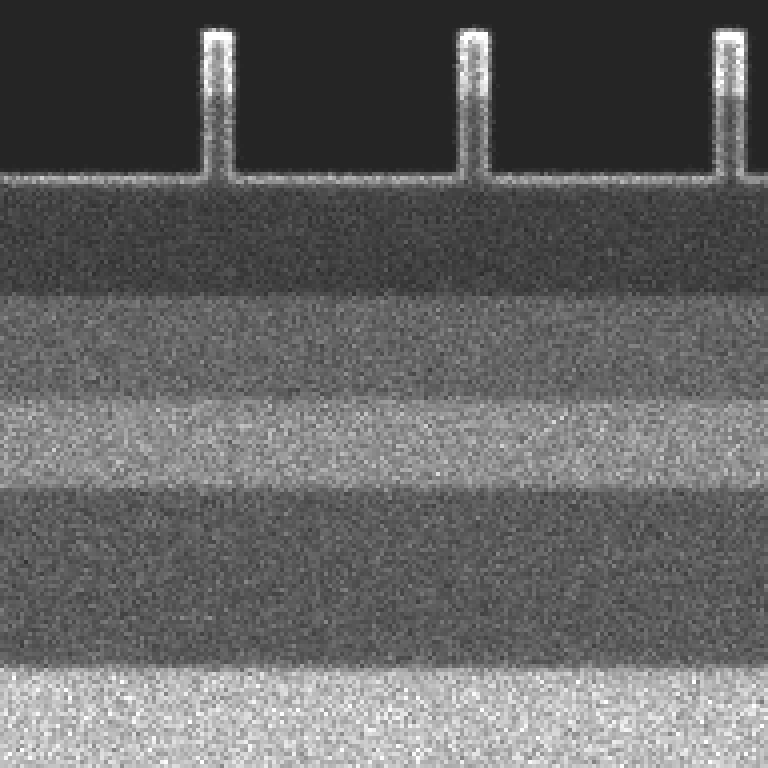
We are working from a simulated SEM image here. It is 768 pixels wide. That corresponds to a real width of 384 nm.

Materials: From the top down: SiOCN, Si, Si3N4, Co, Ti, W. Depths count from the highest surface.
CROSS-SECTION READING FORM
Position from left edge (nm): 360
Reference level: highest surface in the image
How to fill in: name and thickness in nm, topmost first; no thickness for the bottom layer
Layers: SiOCN 32, Si 100, Si3N4 52, Co 44, Ti 90, W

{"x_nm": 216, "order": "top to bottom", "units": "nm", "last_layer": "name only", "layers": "empty 72, Si 60, Si3N4 52, Co 44, Ti 90, W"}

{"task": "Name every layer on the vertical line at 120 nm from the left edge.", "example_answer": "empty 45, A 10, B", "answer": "empty 72, Si 60, Si3N4 52, Co 44, Ti 90, W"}